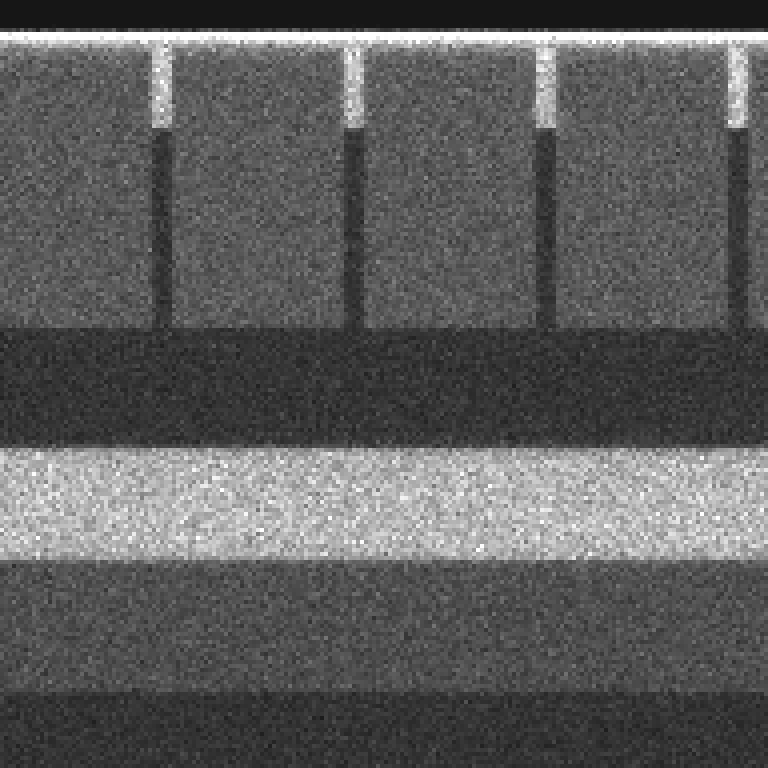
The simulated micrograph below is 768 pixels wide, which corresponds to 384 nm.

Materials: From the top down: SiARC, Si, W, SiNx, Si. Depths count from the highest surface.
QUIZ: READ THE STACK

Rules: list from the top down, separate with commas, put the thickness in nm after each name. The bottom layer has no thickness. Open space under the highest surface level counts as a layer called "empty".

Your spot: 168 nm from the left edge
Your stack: SiARC 148, Si 60, W 56, SiNx 66, Si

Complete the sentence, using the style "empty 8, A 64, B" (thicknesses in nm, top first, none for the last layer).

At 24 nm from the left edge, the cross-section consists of SiARC 148, Si 60, W 56, SiNx 66, Si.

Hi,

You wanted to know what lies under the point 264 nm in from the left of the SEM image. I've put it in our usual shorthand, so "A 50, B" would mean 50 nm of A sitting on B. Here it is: SiARC 148, Si 60, W 56, SiNx 66, Si